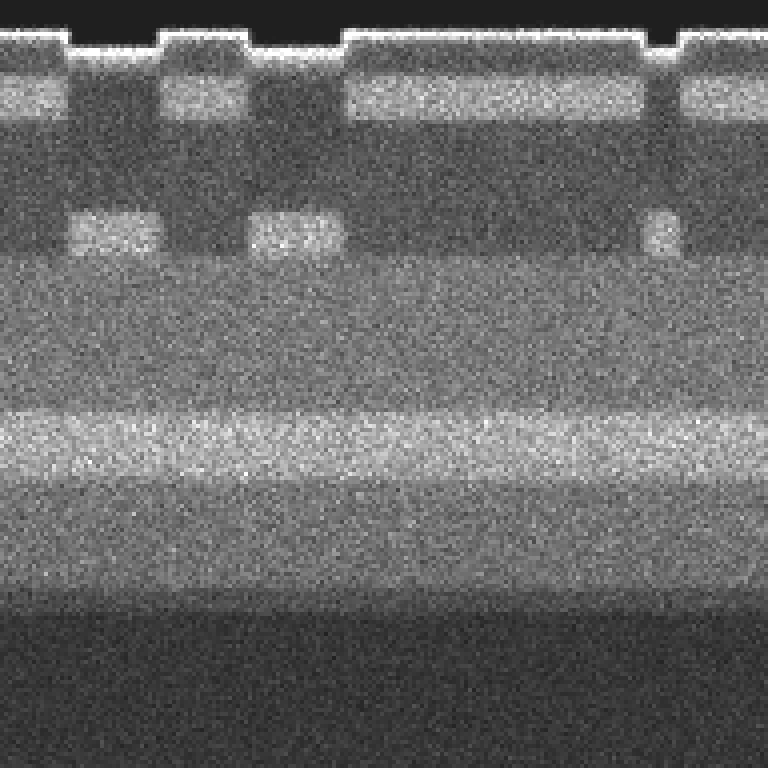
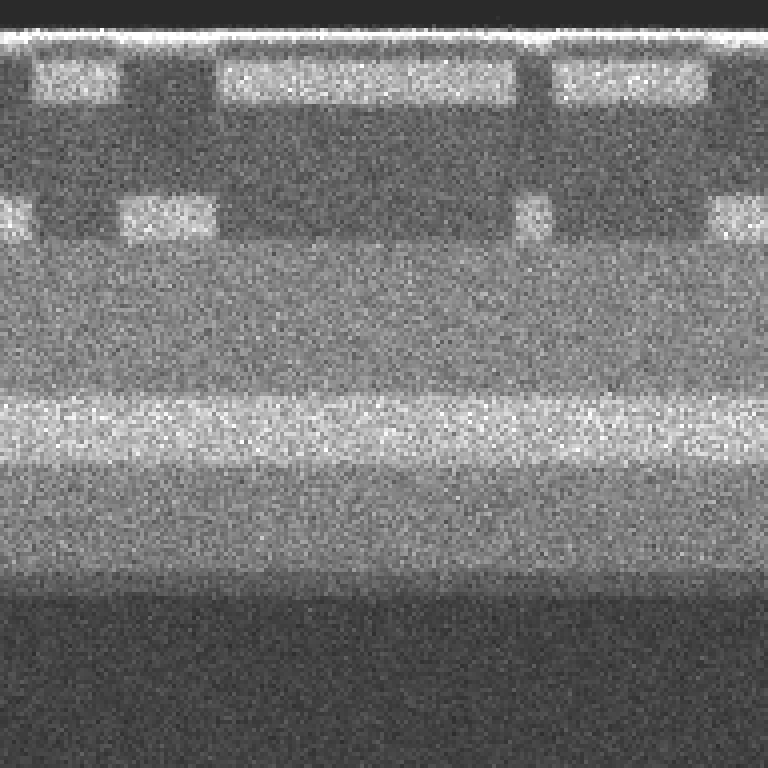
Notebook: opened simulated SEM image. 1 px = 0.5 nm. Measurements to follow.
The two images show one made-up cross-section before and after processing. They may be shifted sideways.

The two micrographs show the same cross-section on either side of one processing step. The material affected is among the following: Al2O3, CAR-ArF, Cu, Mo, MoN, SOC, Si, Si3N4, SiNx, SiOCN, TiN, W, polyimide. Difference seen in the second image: TiN removed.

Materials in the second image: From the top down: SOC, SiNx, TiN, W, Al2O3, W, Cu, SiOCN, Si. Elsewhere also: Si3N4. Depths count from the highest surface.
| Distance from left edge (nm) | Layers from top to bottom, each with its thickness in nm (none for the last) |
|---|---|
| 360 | SOC 10, SiNx 50, TiN 22, W 22, Al2O3 78, W 34, Cu 54, SiOCN 12, Si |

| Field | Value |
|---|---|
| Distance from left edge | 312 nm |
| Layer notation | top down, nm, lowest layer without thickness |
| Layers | TiN 14, W 22, Si3N4 68, Al2O3 78, W 34, Cu 54, SiOCN 12, Si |